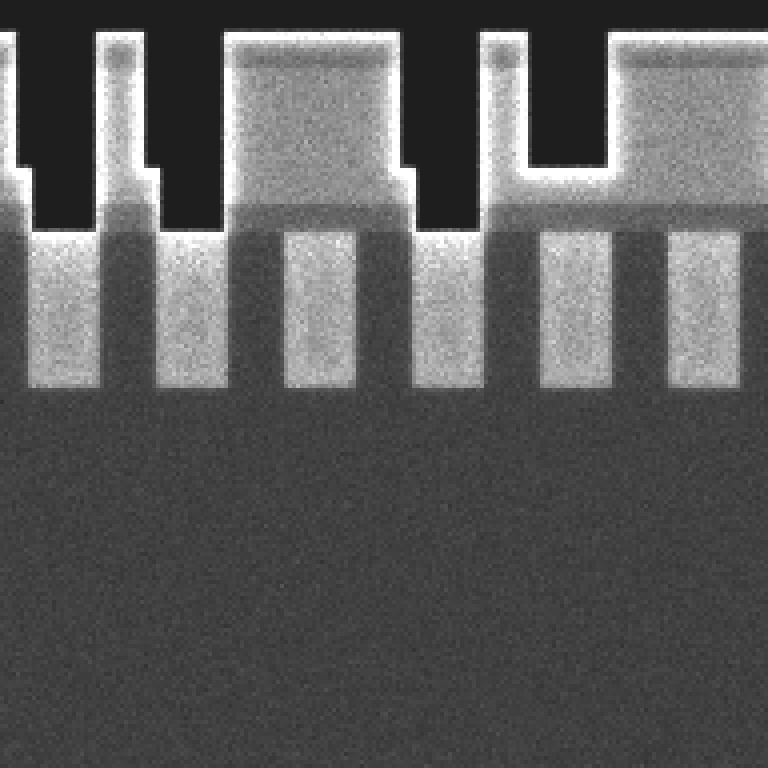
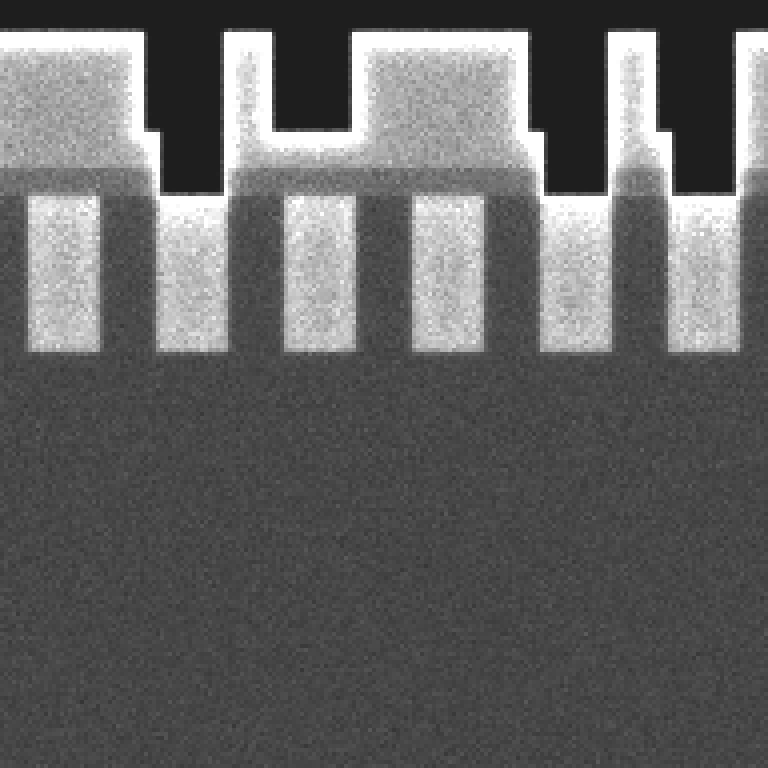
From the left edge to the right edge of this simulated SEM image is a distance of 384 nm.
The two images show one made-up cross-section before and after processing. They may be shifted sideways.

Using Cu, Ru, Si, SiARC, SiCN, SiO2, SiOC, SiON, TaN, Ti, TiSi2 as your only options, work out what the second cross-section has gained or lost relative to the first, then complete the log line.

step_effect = removed SiARC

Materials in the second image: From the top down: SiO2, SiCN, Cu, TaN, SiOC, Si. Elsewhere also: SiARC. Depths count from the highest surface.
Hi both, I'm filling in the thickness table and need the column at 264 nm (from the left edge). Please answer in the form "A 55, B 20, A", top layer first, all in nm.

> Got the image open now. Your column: empty 50, SiO2 18, SiCN 14, SiOC 104, Si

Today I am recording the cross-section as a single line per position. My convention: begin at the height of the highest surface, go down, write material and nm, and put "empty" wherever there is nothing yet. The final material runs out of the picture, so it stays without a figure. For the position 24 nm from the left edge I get SiO2 68, SiCN 14, Cu 68, TaN 10, SiOC 26, Si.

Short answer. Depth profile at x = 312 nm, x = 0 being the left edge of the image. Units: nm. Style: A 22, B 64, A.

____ SiO2 68, SiCN 14, SiOC 104, Si